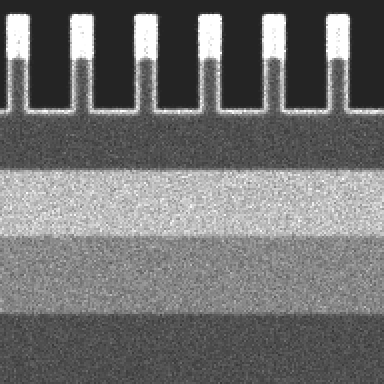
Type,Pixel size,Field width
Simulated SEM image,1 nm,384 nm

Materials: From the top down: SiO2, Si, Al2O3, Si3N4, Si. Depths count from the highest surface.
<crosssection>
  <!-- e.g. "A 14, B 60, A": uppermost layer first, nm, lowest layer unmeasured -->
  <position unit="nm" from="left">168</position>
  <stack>empty 94, Si 60, Al2O3 66, Si3N4 78, Si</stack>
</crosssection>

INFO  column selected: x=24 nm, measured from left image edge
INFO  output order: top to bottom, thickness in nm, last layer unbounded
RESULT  SiO2 42, Si 112, Al2O3 66, Si3N4 78, Si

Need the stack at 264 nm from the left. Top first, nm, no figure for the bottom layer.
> SiO2 42, Si 112, Al2O3 66, Si3N4 78, Si